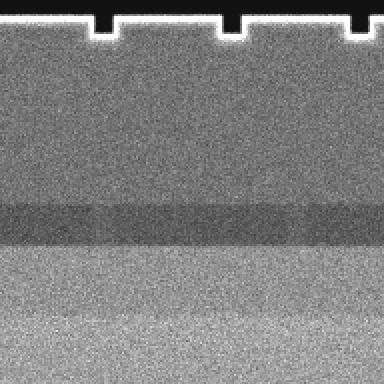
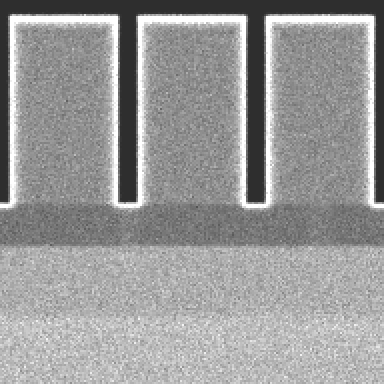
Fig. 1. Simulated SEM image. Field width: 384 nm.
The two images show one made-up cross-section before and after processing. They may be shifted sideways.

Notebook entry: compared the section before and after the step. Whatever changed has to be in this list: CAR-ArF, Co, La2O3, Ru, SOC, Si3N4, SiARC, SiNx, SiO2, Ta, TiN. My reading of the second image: SOC removed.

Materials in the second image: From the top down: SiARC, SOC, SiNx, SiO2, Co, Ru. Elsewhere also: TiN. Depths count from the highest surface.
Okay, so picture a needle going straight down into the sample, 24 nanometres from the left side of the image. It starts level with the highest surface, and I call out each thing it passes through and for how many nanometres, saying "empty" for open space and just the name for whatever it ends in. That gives SiARC 18, SOC 170, SiNx 42, SiO2 42, Co 28, Ru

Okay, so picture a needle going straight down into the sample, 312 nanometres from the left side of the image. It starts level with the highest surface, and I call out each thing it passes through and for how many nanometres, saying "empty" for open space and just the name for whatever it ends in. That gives SiARC 18, SOC 170, TiN 42, SiO2 42, Co 28, Ru